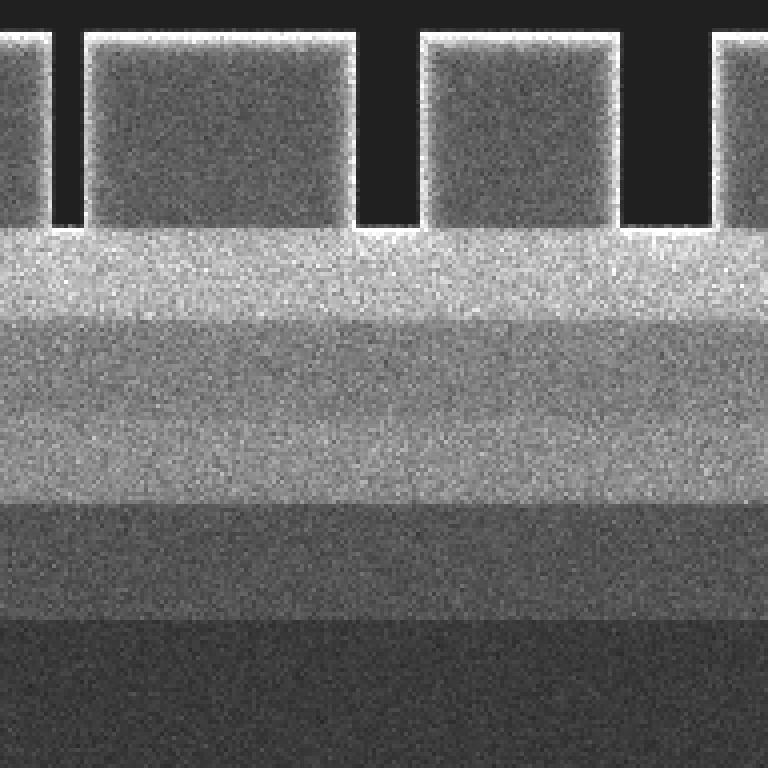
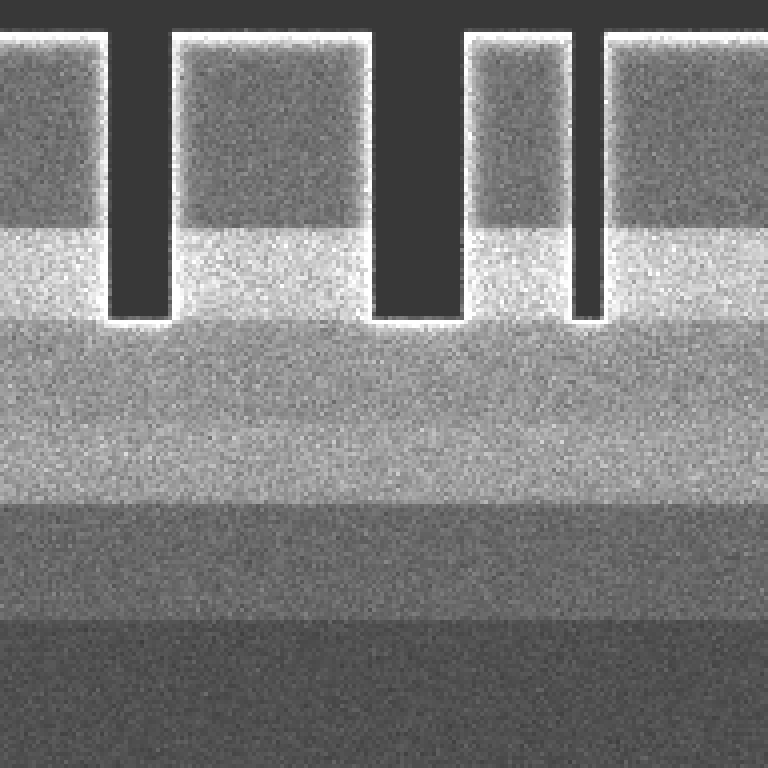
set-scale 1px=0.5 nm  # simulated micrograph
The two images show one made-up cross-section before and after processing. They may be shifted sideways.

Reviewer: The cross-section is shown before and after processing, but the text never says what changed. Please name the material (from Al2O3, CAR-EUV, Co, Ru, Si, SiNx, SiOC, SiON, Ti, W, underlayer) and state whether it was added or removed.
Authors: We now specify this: W, removed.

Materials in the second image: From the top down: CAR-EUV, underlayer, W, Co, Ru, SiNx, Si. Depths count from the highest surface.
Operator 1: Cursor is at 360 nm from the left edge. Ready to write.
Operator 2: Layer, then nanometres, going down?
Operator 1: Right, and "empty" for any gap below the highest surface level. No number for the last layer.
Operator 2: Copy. CAR-EUV 60, underlayer 38, W 46, Co 50, Ru 42, SiNx 58, Si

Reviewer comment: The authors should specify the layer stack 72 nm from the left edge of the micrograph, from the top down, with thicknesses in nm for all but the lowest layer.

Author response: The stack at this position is empty 144, Co 50, Ru 42, SiNx 58, Si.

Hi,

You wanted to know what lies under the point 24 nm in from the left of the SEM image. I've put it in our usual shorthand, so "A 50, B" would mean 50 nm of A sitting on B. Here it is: CAR-EUV 60, underlayer 38, W 46, Co 50, Ru 42, SiNx 58, Si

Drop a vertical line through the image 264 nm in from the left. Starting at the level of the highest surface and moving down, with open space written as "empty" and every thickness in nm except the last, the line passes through CAR-EUV 60, underlayer 38, W 46, Co 50, Ru 42, SiNx 58, Si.